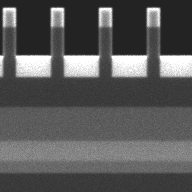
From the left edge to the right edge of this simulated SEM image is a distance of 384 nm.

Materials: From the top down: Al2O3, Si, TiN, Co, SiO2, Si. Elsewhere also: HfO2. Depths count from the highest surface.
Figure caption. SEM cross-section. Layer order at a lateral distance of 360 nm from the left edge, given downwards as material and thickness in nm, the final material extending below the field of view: empty 96, HfO2 42, Si 60, TiN 68, Co 40, SiO2 24, Si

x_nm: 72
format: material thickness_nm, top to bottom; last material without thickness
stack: empty 96, HfO2 42, Si 60, TiN 68, Co 40, SiO2 24, Si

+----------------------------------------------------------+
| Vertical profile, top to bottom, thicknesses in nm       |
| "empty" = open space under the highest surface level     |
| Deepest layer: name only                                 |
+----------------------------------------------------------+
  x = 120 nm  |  Al2O3 38, Si 160, TiN 68, Co 40, SiO2 24, Si